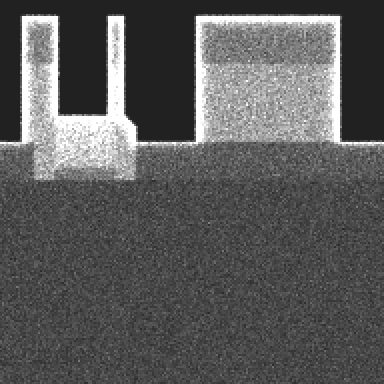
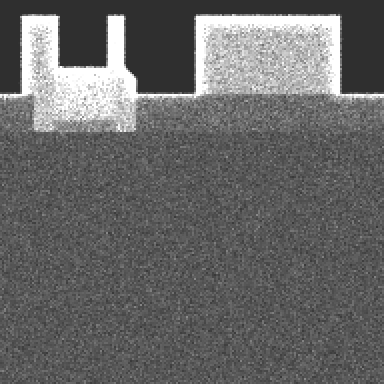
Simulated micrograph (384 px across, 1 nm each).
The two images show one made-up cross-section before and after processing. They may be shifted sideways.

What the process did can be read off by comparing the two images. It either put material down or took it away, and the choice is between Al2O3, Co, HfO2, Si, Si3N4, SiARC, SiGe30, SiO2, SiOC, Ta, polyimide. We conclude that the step removed SiARC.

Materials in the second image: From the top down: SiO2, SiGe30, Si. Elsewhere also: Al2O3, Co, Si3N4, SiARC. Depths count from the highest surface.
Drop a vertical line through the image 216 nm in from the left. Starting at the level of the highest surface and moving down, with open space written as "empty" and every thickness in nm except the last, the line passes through SiO2 78, SiGe30 38, Si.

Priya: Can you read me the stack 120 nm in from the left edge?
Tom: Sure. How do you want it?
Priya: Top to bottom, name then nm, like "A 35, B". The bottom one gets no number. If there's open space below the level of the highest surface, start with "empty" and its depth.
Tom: SiO2 52, Al2O3 64, Si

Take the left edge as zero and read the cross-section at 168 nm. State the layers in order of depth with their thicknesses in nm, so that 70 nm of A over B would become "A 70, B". empty 78, SiGe30 38, Si